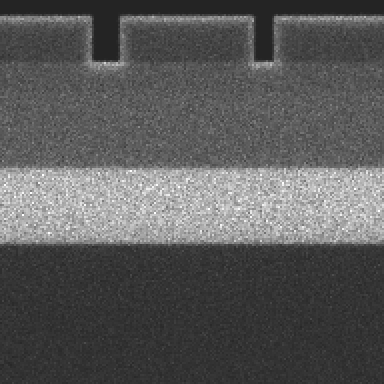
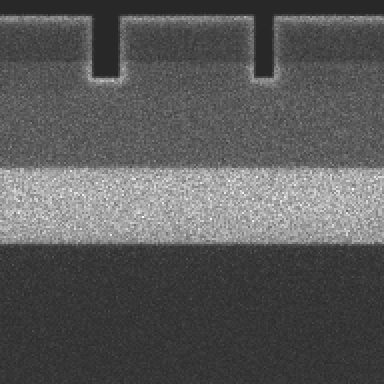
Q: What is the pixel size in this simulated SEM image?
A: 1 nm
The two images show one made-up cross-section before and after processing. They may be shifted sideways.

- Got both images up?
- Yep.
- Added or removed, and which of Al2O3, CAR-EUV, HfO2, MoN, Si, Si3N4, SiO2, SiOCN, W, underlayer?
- removed, SiO2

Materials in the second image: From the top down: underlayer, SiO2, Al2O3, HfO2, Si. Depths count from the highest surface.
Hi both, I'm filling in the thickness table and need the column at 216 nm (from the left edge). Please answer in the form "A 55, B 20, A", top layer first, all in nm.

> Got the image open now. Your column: underlayer 46, SiO2 30, Al2O3 76, HfO2 76, Si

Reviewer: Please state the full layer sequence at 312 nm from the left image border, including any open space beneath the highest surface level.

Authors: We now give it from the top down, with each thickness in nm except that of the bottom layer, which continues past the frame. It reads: underlayer 46, SiO2 30, Al2O3 76, HfO2 76, Si